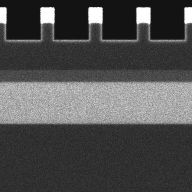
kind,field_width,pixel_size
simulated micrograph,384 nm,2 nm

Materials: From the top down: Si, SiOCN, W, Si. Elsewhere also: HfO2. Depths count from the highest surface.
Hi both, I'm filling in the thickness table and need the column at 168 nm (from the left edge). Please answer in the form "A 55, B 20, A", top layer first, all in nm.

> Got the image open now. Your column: empty 64, Si 60, SiOCN 24, W 84, Si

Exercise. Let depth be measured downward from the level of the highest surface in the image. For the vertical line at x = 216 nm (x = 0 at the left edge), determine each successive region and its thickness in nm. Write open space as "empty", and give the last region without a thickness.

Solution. empty 64, Si 60, SiOCN 24, W 84, Si